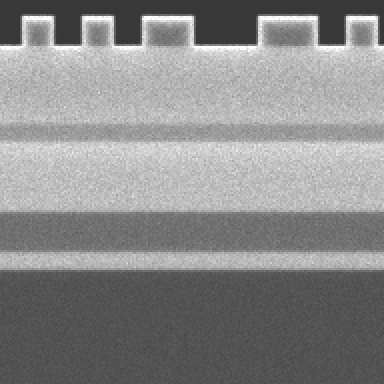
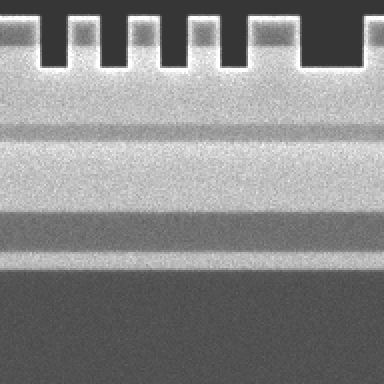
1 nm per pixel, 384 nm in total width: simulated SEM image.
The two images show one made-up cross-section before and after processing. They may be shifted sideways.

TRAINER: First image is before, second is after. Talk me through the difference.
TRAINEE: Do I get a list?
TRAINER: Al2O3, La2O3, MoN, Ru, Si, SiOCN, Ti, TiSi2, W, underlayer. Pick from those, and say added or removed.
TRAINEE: removed: Ru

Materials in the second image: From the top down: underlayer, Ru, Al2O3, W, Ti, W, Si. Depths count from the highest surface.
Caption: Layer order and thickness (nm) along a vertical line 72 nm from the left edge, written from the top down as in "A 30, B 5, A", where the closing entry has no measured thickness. underlayer 30, Ru 78, Al2O3 18, W 70, Ti 40, W 18, Si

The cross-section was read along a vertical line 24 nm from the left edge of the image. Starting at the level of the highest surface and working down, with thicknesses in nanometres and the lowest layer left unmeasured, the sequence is underlayer 30, Ru 78, Al2O3 18, W 70, Ti 40, W 18, Si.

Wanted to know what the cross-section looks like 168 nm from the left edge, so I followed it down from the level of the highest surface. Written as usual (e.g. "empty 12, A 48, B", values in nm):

empty 52, Ru 56, Al2O3 18, W 70, Ti 40, W 18, Si